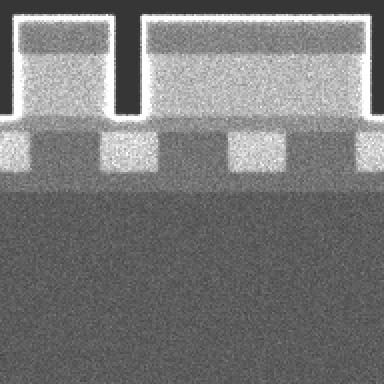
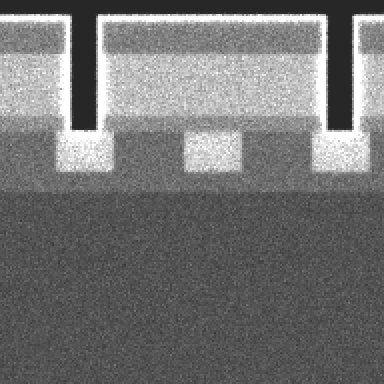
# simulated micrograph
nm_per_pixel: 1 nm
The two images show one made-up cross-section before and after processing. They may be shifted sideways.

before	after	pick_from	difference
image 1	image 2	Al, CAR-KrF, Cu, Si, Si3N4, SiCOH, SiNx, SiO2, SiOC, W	Si3N4 removed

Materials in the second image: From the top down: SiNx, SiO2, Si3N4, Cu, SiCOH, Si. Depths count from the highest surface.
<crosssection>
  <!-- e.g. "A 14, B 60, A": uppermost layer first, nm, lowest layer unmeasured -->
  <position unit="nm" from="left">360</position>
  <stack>SiNx 38, SiO2 62, Si3N4 16, Cu 40, SiCOH 20, Si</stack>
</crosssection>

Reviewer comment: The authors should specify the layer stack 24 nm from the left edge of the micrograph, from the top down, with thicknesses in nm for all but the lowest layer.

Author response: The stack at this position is SiNx 38, SiO2 62, Si3N4 16, SiCOH 60, Si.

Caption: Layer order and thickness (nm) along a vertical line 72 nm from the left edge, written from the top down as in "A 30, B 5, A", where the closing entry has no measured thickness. empty 116, Cu 40, SiCOH 20, Si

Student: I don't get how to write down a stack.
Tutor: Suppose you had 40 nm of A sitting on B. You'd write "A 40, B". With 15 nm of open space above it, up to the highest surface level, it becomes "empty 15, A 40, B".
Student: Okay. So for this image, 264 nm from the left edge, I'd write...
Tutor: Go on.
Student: SiNx 38, SiO2 62, Si3N4 16, SiCOH 60, Si